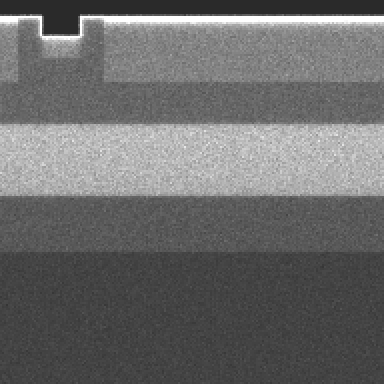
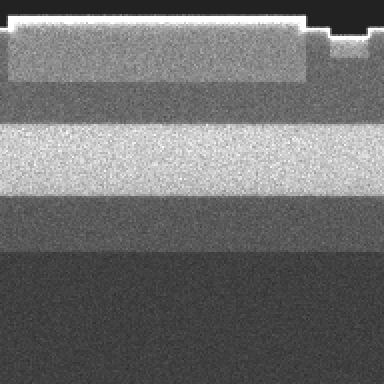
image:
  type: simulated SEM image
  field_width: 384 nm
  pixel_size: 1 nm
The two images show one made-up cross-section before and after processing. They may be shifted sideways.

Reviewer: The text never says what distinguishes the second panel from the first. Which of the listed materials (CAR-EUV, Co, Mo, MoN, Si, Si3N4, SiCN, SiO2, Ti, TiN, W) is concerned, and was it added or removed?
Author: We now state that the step removed TiN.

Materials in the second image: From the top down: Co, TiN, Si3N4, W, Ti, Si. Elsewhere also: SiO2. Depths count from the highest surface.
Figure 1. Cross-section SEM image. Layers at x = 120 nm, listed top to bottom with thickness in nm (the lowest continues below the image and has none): SiO2 66, Si3N4 42, W 72, Ti 56, Si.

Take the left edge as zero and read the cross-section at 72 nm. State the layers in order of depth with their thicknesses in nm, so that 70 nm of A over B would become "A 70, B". SiO2 66, Si3N4 42, W 72, Ti 56, Si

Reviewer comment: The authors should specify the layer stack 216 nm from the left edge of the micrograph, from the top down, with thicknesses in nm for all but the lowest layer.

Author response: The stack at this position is SiO2 66, Si3N4 42, W 72, Ti 56, Si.